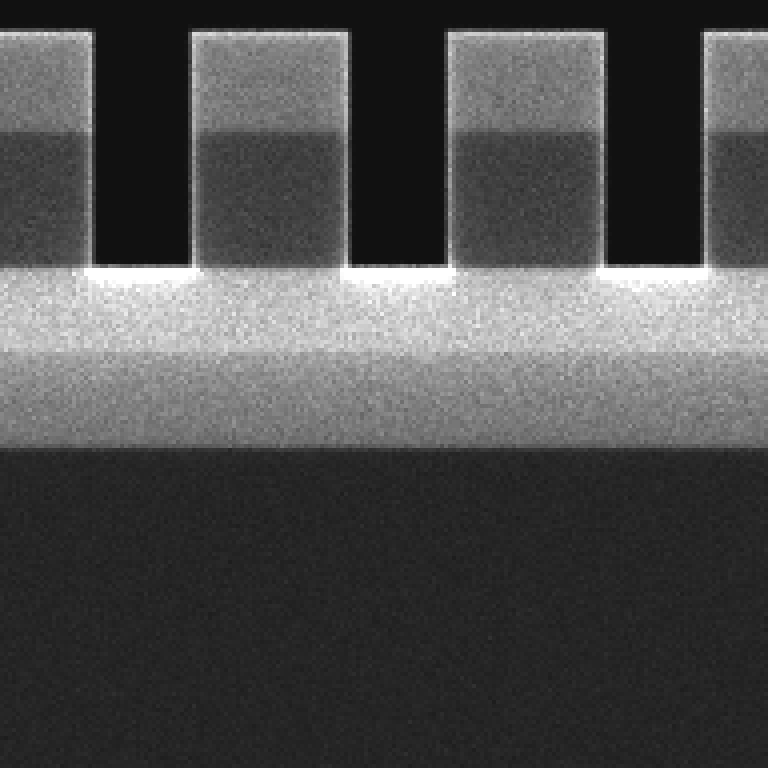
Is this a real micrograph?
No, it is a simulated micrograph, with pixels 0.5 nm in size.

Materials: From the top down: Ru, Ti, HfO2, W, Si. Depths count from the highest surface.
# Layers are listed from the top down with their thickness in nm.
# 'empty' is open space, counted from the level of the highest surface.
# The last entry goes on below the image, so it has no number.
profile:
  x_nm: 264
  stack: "Ru 50, Ti 68, HfO2 42, W 48, Si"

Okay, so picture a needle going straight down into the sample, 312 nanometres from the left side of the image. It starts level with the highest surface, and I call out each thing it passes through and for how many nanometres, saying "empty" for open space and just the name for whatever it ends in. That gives empty 118, HfO2 42, W 48, Si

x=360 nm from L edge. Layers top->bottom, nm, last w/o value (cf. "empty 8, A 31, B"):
Ru 50, Ti 68, HfO2 42, W 48, Si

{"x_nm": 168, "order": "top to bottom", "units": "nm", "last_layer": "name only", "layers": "Ru 50, Ti 68, HfO2 42, W 48, Si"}